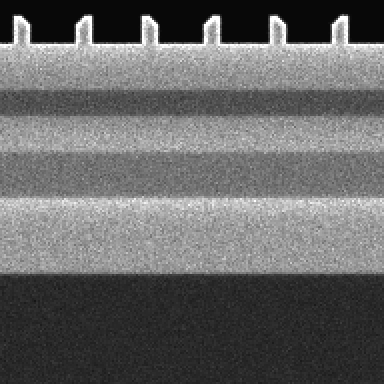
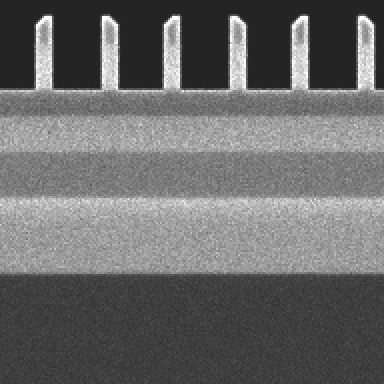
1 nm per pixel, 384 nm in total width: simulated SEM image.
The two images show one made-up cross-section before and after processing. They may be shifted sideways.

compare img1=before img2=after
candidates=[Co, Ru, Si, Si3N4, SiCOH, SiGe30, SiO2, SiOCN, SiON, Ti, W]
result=removed:Ru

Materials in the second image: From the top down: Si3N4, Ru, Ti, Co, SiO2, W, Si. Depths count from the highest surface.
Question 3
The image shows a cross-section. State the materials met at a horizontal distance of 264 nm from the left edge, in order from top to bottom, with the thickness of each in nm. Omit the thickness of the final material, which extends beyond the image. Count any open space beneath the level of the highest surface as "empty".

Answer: empty 74, Ti 26, Co 36, SiO2 46, W 76, Si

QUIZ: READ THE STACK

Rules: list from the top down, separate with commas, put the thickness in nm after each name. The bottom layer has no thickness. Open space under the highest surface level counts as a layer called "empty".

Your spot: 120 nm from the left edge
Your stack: empty 74, Ti 26, Co 36, SiO2 46, W 76, Si